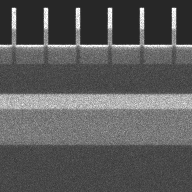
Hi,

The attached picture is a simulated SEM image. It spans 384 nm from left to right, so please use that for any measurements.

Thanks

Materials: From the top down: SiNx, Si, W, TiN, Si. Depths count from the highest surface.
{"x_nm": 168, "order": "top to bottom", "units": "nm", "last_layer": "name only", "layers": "empty 74, SiNx 38, Si 60, W 30, TiN 72, Si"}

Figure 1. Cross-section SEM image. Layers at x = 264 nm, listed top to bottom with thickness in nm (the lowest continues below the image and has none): empty 74, SiNx 38, Si 60, W 30, TiN 72, Si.